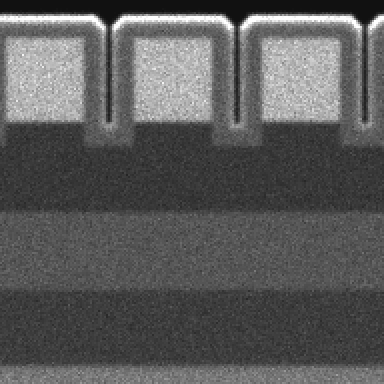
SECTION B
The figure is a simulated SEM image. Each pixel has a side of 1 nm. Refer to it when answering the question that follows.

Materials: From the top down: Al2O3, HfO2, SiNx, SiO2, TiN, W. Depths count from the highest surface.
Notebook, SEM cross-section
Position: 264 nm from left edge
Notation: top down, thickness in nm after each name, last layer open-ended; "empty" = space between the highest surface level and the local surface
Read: Al2O3 22, HfO2 84, SiNx 90, SiO2 78, TiN 76, W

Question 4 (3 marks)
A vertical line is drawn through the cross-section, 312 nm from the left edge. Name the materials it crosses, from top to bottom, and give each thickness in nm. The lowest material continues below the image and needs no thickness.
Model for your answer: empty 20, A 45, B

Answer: Al2O3 22, HfO2 84, SiNx 90, SiO2 78, TiN 76, W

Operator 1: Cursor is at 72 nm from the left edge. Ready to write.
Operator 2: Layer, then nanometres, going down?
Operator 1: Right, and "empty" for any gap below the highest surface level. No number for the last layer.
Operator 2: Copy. Al2O3 22, HfO2 84, SiNx 90, SiO2 78, TiN 76, W